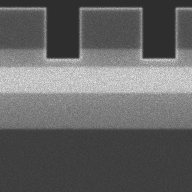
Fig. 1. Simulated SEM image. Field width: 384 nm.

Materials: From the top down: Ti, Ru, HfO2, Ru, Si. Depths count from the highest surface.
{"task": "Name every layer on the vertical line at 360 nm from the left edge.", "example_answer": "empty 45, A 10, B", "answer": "Ti 82, Ru 36, HfO2 52, Ru 72, Si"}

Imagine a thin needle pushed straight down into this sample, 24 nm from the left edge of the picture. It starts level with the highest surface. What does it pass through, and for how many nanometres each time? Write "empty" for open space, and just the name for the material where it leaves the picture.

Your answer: Ti 82, Ru 36, HfO2 52, Ru 72, Si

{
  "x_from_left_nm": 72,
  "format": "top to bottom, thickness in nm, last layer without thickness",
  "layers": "Ti 82, Ru 36, HfO2 52, Ru 72, Si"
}